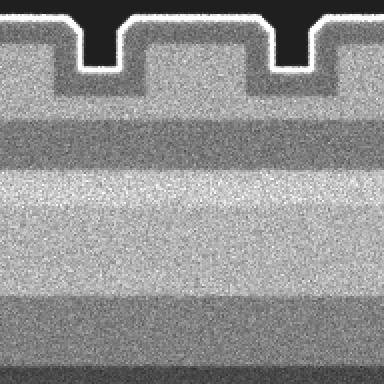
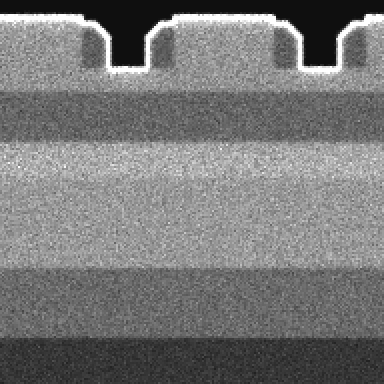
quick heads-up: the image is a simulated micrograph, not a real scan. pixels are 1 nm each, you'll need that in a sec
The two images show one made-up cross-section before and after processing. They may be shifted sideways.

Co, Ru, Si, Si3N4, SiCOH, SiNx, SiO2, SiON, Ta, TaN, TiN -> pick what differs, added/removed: SiNx removed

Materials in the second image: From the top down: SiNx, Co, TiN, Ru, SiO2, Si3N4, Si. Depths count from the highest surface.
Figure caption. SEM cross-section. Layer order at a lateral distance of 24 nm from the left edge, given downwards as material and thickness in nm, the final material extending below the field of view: Co 76, TiN 50, Ru 36, SiO2 90, Si3N4 70, Si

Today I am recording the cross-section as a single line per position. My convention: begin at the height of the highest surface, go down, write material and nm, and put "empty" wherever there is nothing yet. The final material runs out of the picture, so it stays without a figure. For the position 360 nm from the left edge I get empty 6, SiNx 46, Co 24, TiN 50, Ru 36, SiO2 90, Si3N4 70, Si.